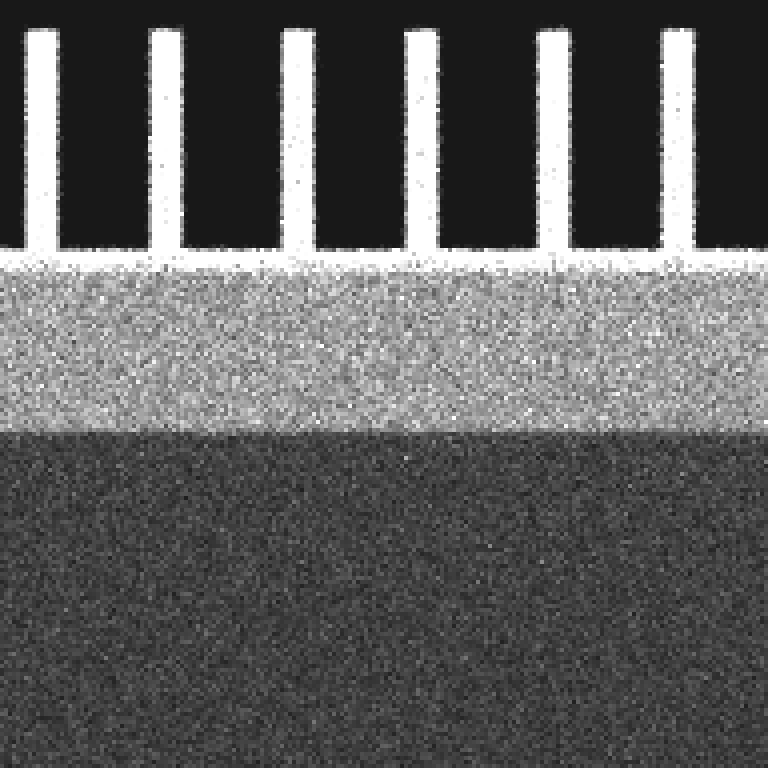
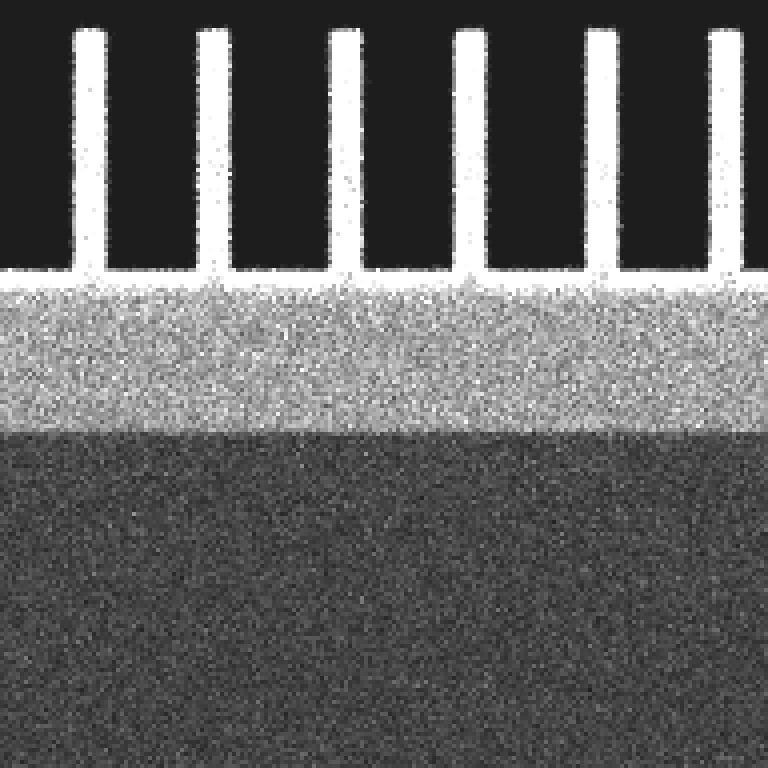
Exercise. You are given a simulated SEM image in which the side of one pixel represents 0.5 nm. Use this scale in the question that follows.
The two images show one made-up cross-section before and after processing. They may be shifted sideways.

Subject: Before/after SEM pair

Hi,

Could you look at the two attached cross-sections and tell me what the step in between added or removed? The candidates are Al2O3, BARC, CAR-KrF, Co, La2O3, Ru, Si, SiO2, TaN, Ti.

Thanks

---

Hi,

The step removed Co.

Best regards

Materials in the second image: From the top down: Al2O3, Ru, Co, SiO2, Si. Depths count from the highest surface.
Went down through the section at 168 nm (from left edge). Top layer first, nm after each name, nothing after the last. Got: Al2O3 50, Ru 60, Co 10, SiO2 80, Si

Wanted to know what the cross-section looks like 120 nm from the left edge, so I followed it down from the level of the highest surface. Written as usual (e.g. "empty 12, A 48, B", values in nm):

empty 120, SiO2 80, Si